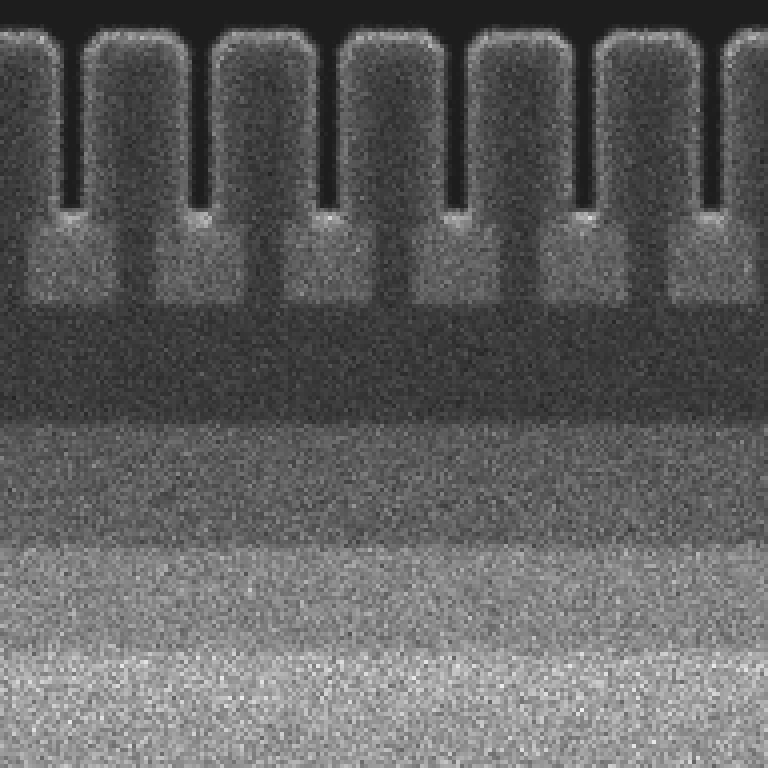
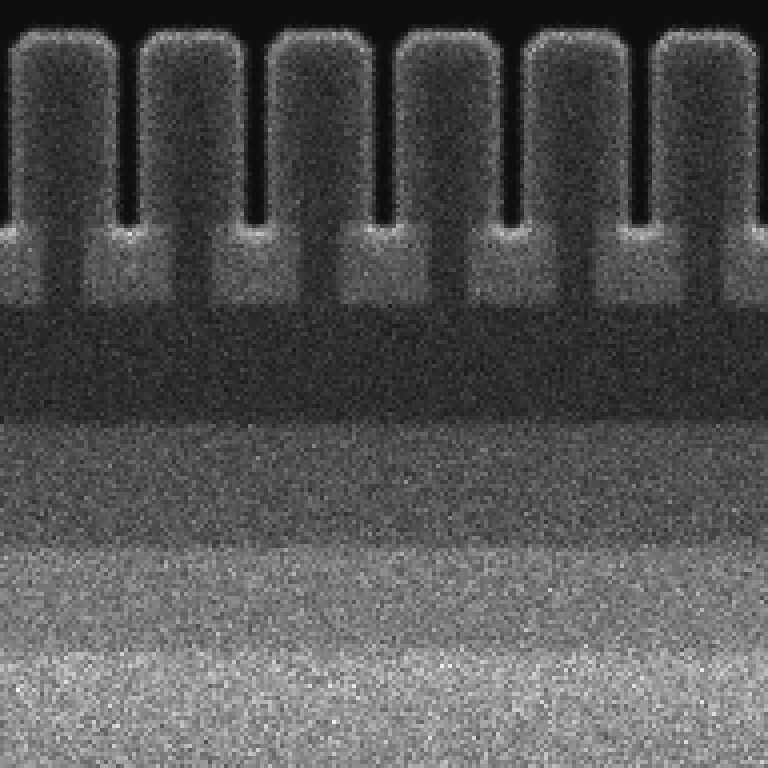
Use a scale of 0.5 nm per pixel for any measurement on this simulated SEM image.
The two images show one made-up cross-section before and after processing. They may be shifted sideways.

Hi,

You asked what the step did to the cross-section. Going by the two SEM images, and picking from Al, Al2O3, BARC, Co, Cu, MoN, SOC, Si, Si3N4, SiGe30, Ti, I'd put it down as SOC, removed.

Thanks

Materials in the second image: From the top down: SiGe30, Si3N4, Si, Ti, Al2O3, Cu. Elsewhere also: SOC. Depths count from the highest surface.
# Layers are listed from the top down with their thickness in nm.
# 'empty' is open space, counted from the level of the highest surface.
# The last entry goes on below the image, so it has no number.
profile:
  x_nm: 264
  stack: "empty 6, SiGe30 90, Si3N4 40, Si 60, Ti 62, Al2O3 52, Cu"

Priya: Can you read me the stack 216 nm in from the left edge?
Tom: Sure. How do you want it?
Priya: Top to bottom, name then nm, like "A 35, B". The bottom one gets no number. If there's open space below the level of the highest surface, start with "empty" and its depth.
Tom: SiGe30 16, Si 180, Ti 62, Al2O3 52, Cu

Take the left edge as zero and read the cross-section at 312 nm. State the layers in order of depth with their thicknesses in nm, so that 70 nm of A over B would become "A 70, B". empty 8, SiGe30 88, Si3N4 40, Si 60, Ti 62, Al2O3 52, Cu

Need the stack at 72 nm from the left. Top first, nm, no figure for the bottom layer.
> empty 6, SiGe30 90, Si3N4 40, Si 60, Ti 62, Al2O3 52, Cu